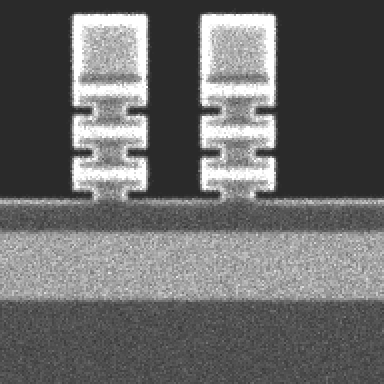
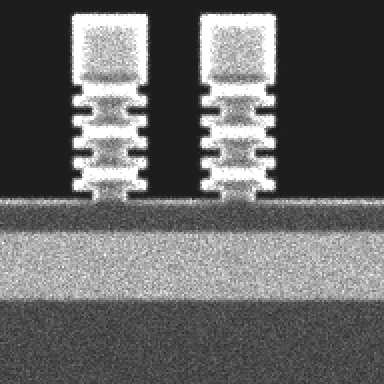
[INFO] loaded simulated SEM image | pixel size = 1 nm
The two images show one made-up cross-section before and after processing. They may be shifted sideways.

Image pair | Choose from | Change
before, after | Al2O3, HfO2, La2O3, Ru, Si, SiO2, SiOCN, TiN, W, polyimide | W (removed)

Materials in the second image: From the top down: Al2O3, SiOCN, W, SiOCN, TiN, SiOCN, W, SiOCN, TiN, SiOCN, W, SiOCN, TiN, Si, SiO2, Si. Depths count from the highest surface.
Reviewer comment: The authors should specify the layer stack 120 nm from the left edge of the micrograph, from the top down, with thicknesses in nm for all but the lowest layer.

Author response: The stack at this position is Al2O3 58, SiOCN 10, W 12, SiOCN 10, TiN 10, SiOCN 10, W 12, SiOCN 10, TiN 10, SiOCN 10, W 12, SiOCN 10, TiN 10, Si 32, SiO2 68, Si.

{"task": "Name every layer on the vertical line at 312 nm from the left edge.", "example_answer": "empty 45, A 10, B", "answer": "empty 184, Si 32, SiO2 68, Si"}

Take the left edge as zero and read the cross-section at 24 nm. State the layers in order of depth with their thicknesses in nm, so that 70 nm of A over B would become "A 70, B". empty 184, Si 32, SiO2 68, Si